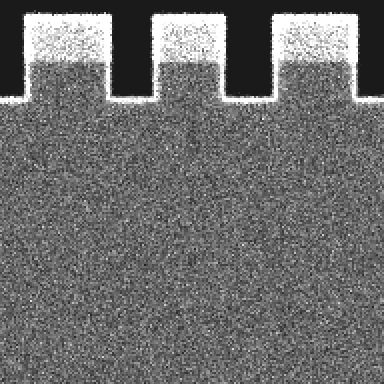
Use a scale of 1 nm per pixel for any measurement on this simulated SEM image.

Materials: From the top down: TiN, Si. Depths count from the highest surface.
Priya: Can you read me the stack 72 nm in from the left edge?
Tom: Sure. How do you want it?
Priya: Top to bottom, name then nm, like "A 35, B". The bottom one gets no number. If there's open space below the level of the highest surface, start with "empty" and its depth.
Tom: TiN 46, Si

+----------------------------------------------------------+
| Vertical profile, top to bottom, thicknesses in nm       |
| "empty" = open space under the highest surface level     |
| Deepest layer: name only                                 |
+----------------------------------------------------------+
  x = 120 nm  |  empty 82, Si